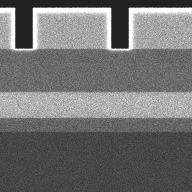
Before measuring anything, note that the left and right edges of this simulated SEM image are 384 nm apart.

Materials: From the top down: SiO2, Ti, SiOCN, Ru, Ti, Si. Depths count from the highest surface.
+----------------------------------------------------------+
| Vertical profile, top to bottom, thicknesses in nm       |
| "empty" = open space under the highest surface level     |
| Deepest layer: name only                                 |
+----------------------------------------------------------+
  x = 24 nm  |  SiO2 82, Ti 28, SiOCN 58, Ru 52, Ti 28, Si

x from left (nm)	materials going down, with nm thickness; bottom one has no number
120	SiO2 82, Ti 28, SiOCN 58, Ru 52, Ti 28, Si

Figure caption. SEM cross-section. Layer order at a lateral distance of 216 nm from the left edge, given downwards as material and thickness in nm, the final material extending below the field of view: SiO2 82, Ti 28, SiOCN 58, Ru 52, Ti 28, Si